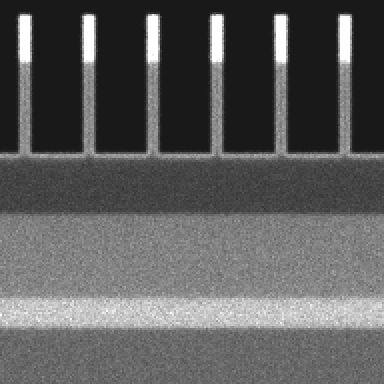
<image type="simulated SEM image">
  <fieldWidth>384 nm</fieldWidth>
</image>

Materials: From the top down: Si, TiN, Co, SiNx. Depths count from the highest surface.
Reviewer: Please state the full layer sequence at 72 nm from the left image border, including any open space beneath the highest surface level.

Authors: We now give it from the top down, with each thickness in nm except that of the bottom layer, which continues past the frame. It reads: empty 138, Si 60, TiN 84, Co 30, SiNx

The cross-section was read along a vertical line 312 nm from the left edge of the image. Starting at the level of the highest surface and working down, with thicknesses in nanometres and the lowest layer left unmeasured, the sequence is empty 138, Si 60, TiN 84, Co 30, SiNx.